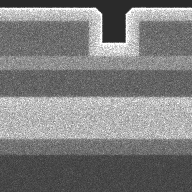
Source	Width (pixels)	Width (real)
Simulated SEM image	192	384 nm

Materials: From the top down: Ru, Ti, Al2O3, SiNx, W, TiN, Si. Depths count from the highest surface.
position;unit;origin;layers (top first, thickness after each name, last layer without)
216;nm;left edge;empty 70, Ru 26, Al2O3 28, SiNx 54, W 84, TiN 32, Si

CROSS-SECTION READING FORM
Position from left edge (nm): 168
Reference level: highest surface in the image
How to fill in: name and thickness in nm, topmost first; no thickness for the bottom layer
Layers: Ru 26, Ti 70, Al2O3 28, SiNx 54, W 84, TiN 32, Si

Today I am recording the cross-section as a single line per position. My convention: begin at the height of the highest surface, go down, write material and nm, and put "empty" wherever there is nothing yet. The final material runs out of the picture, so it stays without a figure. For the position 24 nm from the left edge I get Ru 26, Ti 70, Al2O3 28, SiNx 54, W 84, TiN 32, Si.